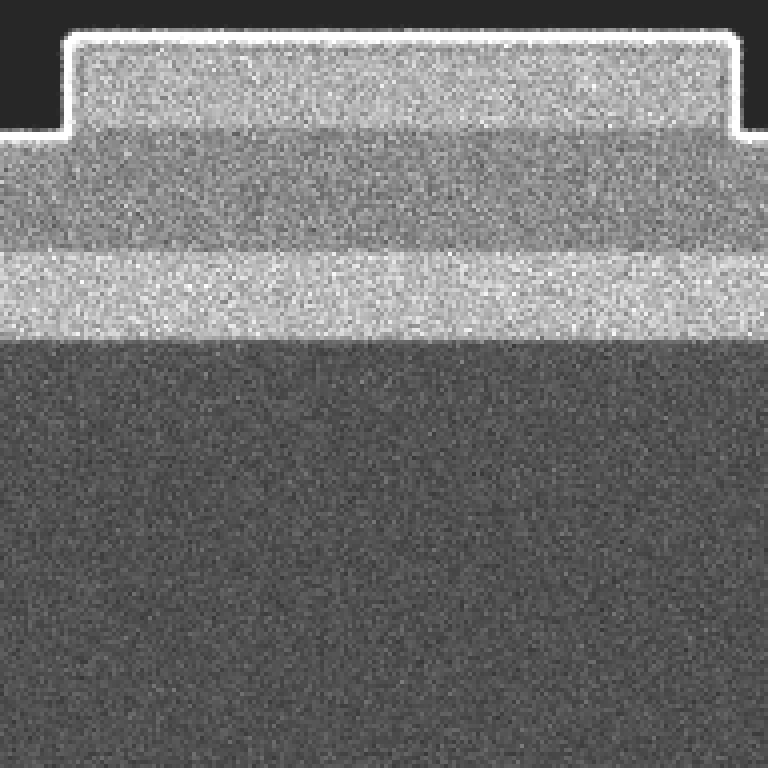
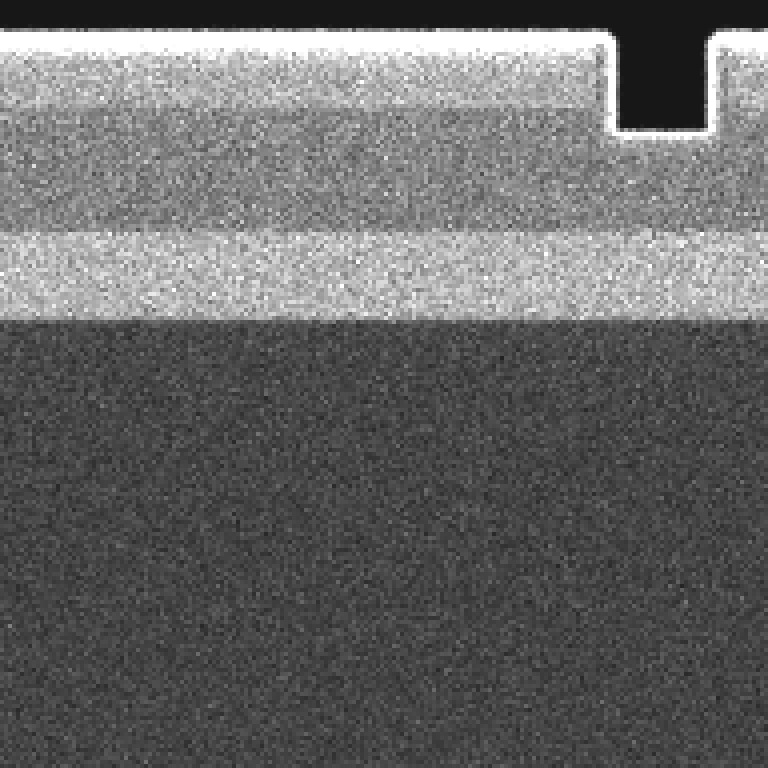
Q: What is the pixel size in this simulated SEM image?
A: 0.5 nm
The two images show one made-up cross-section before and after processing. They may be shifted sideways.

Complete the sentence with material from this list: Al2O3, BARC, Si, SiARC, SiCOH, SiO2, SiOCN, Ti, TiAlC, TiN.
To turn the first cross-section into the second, SiOCN must be removed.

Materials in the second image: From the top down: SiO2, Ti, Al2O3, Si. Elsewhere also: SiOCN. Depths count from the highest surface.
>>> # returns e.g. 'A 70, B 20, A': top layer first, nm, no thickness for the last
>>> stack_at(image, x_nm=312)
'empty 50, Ti 50, Al2O3 44, Si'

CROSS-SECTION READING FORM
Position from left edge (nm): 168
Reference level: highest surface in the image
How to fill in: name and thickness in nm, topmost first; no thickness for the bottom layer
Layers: SiO2 38, Ti 62, Al2O3 44, Si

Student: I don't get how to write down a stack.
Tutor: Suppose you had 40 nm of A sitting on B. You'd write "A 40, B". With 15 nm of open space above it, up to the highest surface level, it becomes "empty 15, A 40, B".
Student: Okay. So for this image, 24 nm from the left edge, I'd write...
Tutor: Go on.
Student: SiO2 38, Ti 62, Al2O3 44, Si